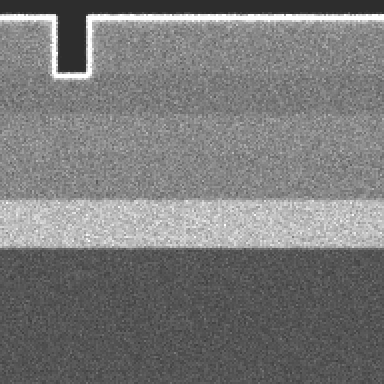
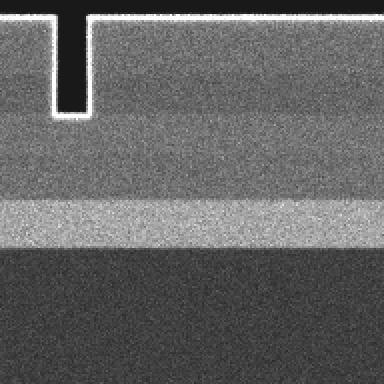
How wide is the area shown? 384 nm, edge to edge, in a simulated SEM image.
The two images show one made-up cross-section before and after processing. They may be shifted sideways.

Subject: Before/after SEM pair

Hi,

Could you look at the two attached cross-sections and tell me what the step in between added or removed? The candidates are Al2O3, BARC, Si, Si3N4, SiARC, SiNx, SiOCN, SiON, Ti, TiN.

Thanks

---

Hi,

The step removed SiNx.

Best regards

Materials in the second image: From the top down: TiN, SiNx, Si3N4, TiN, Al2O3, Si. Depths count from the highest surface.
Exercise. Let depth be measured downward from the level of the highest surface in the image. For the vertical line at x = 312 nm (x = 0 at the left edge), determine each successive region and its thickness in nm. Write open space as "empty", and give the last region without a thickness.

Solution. TiN 58, SiNx 40, Si3N4 40, TiN 46, Al2O3 48, Si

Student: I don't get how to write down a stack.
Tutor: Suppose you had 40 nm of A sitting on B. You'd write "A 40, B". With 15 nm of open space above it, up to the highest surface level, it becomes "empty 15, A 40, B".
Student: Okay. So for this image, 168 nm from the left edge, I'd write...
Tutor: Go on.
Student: TiN 58, SiNx 40, Si3N4 40, TiN 46, Al2O3 48, Si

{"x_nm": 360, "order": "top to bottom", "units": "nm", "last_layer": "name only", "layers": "TiN 58, SiNx 40, Si3N4 40, TiN 46, Al2O3 48, Si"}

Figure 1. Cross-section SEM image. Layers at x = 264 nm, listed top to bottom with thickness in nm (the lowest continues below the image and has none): TiN 58, SiNx 40, Si3N4 40, TiN 46, Al2O3 48, Si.